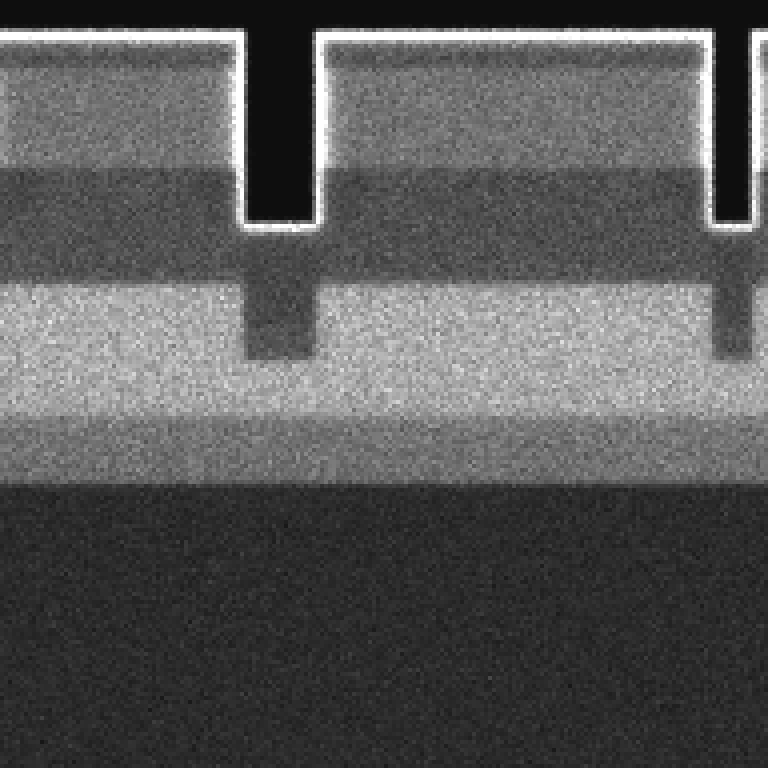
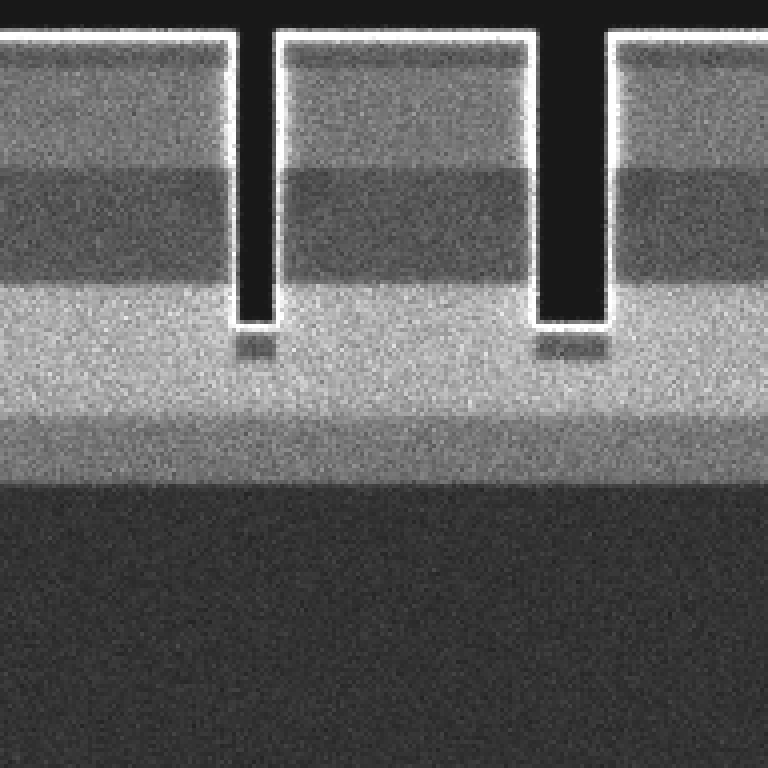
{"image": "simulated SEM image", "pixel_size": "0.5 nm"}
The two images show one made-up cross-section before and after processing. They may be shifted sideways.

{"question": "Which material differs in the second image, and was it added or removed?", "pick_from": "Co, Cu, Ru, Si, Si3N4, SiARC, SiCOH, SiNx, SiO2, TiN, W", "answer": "SiNx, removed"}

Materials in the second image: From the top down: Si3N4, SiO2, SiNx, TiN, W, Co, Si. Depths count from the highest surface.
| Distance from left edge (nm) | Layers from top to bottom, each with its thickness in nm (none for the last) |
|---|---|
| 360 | Si3N4 18, SiO2 50, TiN 58, W 66, Co 34, Si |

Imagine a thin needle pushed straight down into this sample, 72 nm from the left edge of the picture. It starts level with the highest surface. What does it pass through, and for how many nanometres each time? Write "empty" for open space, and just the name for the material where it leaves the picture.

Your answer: Si3N4 18, SiO2 50, TiN 58, W 66, Co 34, Si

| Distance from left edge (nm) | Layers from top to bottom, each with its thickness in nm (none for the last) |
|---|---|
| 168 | Si3N4 18, SiO2 50, TiN 58, W 66, Co 34, Si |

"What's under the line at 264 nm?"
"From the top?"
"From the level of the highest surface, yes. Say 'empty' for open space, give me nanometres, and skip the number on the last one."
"Si3N4 18, SiO2 50, SiNx 28, TiN 30, W 66, Co 34, Si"